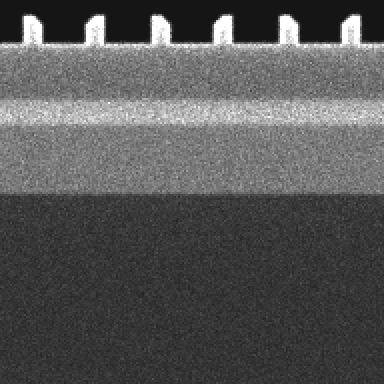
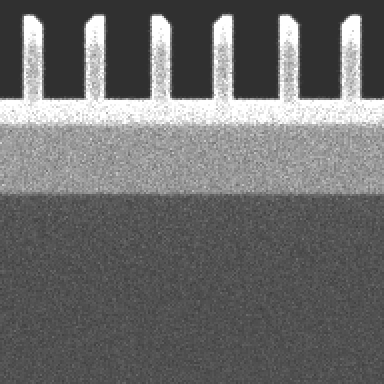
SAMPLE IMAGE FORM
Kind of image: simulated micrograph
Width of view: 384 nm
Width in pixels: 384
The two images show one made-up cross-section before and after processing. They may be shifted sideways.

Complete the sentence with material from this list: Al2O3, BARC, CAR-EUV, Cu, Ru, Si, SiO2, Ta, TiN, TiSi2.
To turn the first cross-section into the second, TiN must be removed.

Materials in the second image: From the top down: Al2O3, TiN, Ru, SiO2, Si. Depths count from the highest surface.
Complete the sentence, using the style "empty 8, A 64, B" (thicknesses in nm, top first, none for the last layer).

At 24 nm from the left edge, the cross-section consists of Al2O3 28, TiN 56, Ru 24, SiO2 70, Si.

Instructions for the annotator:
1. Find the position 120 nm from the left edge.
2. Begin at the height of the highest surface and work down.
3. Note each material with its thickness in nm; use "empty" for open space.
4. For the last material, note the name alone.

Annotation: empty 84, Ru 24, SiO2 70, Si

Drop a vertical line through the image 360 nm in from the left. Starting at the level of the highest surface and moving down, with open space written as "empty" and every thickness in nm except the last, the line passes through empty 84, Ru 24, SiO2 70, Si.